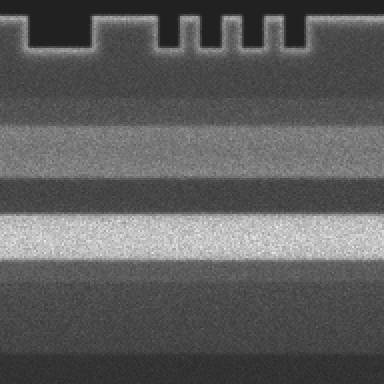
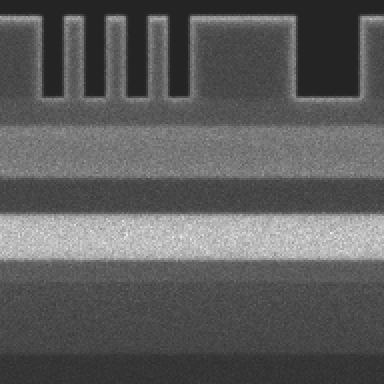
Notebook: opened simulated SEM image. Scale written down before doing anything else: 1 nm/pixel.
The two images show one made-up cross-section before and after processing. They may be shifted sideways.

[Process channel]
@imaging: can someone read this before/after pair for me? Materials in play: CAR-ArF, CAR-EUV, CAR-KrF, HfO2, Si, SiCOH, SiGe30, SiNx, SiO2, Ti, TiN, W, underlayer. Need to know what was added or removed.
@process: underlayer removed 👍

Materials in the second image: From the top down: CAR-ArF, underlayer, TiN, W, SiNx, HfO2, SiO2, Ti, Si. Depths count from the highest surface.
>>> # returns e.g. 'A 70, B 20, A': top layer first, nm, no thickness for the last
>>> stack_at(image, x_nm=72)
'CAR-ArF 32, underlayer 50, TiN 28, W 52, SiNx 36, HfO2 46, SiO2 22, Ti 72, Si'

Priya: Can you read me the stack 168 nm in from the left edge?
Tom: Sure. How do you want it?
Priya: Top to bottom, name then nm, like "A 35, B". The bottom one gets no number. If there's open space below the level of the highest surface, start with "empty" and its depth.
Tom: empty 82, TiN 28, W 52, SiNx 36, HfO2 46, SiO2 22, Ti 72, Si